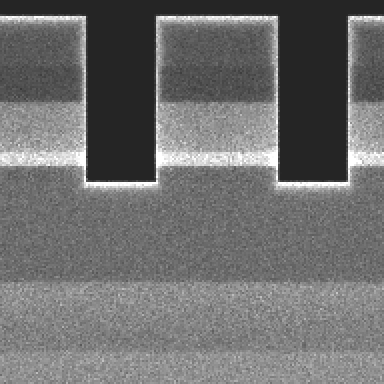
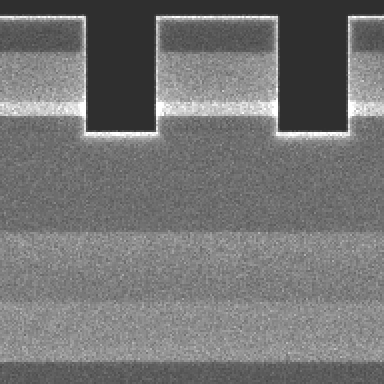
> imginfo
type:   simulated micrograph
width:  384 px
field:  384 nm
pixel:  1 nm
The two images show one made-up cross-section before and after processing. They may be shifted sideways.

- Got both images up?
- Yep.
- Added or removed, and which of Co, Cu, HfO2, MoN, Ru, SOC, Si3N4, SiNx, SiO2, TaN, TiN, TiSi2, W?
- removed, SOC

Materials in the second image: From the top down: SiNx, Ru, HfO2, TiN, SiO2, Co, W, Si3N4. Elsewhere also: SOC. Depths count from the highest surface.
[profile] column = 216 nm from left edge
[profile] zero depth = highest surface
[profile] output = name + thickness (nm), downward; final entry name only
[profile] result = SiNx 36, Ru 50, HfO2 14, TiN 16, SiO2 100, Co 70, W 60, Si3N4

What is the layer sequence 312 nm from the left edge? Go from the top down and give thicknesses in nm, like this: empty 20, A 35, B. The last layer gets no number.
empty 116, SiO2 100, Co 70, W 60, Si3N4